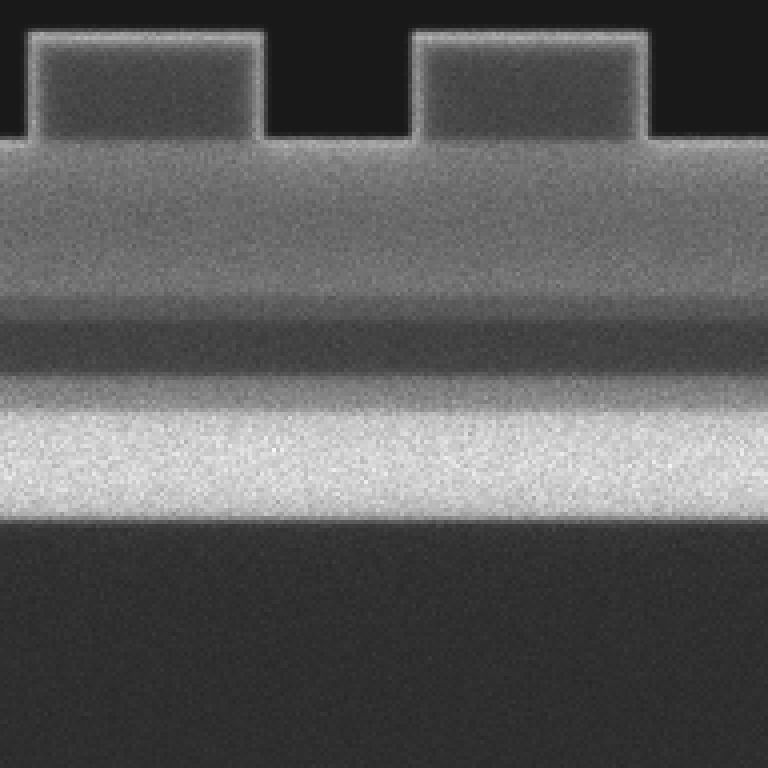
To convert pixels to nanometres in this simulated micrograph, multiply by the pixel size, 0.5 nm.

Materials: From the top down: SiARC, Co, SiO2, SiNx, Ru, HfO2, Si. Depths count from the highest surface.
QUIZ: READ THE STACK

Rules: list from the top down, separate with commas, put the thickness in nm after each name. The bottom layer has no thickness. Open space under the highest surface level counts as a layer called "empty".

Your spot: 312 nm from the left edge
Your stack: SiARC 54, Co 78, SiO2 12, SiNx 28, Ru 18, HfO2 54, Si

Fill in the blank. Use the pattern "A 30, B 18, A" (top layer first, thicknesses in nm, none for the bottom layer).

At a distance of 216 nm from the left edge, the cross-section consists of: SiARC 54, Co 78, SiO2 12, SiNx 28, Ru 18, HfO2 54, Si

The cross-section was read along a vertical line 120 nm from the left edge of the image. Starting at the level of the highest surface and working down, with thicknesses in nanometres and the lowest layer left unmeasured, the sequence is SiARC 54, Co 78, SiO2 12, SiNx 28, Ru 18, HfO2 54, Si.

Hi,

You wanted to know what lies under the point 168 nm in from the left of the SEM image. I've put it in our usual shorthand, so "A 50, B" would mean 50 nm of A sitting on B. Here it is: empty 54, Co 78, SiO2 12, SiNx 28, Ru 18, HfO2 54, Si